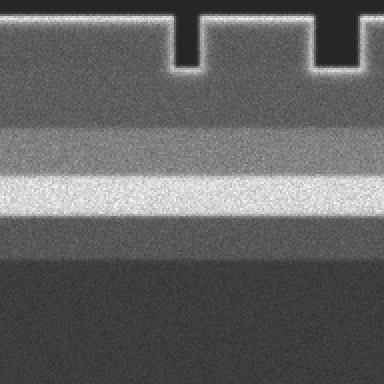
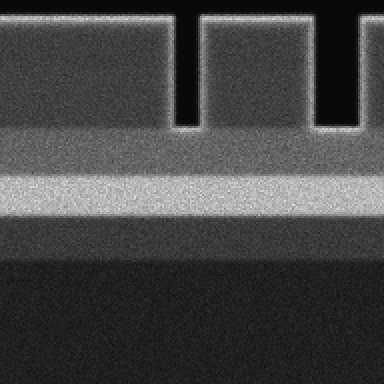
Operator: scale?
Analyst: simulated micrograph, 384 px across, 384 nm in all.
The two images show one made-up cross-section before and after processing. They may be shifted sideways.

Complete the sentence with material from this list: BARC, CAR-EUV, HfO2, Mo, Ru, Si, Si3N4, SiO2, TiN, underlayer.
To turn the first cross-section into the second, underlayer must be removed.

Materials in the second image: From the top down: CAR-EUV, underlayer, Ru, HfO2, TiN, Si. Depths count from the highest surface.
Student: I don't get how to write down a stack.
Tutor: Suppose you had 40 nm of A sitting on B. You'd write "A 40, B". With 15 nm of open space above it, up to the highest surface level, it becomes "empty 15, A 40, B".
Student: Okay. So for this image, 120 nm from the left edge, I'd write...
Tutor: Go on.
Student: CAR-EUV 52, underlayer 60, Ru 48, HfO2 40, TiN 44, Si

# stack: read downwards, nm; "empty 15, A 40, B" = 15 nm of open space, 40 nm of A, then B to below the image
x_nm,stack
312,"CAR-EUV 52, underlayer 60, Ru 48, HfO2 40, TiN 44, Si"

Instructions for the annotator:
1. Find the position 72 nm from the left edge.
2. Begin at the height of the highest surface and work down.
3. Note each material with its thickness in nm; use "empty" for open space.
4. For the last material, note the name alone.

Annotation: CAR-EUV 52, underlayer 60, Ru 48, HfO2 40, TiN 44, Si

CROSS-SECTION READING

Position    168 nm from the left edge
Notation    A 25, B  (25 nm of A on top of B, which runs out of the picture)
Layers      CAR-EUV 52, underlayer 60, Ru 48, HfO2 40, TiN 44, Si